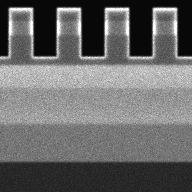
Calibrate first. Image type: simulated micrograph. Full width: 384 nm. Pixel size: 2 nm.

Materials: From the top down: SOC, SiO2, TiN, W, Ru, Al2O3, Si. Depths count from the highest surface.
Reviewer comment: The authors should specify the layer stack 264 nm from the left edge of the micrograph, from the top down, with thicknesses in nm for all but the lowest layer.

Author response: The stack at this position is empty 98, TiN 16, W 46, Ru 72, Al2O3 76, Si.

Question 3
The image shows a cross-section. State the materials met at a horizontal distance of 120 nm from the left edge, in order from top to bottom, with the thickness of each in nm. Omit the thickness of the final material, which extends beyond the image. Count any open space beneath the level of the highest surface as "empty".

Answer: SOC 26, SiO2 28, TiN 60, W 46, Ru 72, Al2O3 76, Si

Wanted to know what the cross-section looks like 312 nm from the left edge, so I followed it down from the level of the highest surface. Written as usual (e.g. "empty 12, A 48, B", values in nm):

SOC 26, SiO2 28, TiN 60, W 46, Ru 72, Al2O3 76, Si